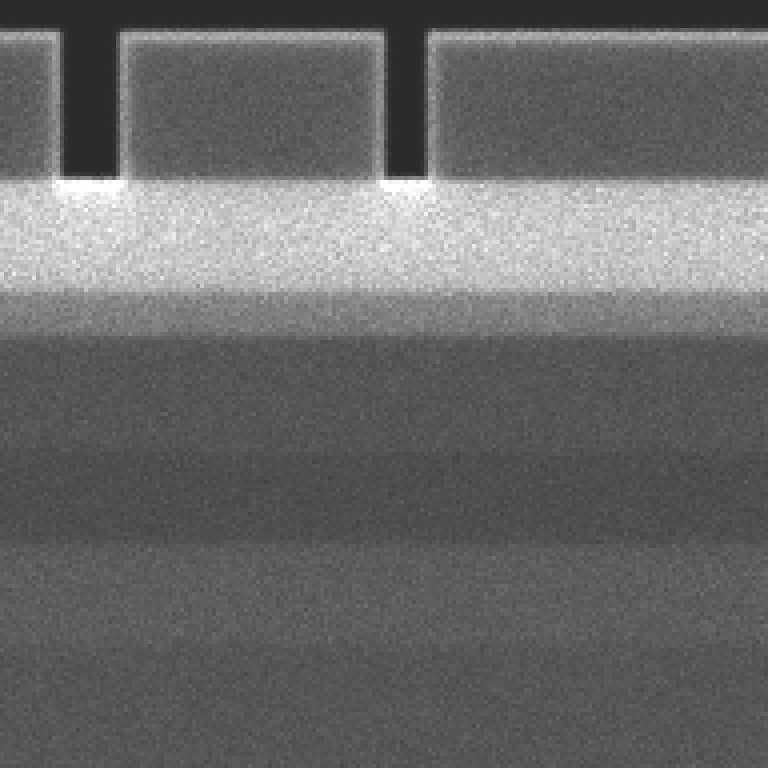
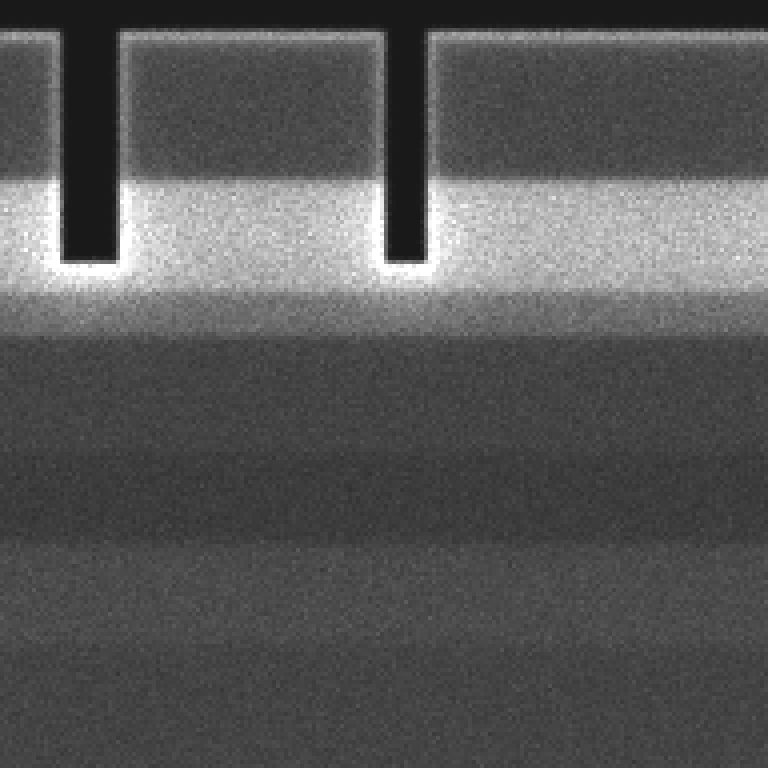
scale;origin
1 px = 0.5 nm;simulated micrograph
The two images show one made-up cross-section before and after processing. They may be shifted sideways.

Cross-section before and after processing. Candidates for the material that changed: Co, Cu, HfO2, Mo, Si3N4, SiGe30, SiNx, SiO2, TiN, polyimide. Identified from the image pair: HfO2 (removed).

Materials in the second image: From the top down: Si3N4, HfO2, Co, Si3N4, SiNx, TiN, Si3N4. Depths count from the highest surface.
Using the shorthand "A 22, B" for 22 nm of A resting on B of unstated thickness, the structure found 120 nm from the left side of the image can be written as Si3N4 74, HfO2 56, Co 22, Si3N4 58, SiNx 46, TiN 50, Si3N4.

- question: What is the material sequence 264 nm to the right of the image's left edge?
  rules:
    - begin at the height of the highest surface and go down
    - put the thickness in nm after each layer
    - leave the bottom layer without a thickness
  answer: Si3N4 74, HfO2 56, Co 22, Si3N4 58, SiNx 46, TiN 50, Si3N4